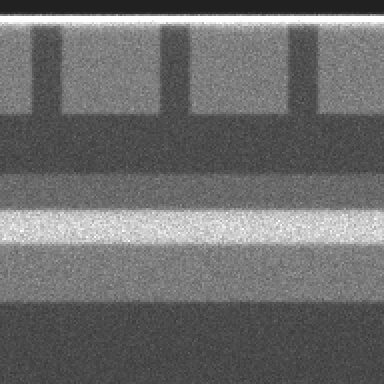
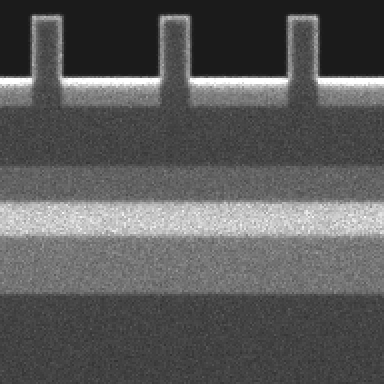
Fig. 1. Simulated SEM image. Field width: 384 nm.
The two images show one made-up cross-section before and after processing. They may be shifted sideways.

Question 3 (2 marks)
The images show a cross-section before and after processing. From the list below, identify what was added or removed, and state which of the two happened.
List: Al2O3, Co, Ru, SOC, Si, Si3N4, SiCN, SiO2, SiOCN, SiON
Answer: SOC was removed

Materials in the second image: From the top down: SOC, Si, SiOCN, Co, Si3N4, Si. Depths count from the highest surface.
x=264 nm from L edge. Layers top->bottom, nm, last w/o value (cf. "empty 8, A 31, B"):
empty 62, SOC 28, Si 60, SiOCN 36, Co 34, Si3N4 58, Si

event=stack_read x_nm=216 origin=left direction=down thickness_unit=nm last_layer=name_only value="empty 62, SOC 28, Si 60, SiOCN 36, Co 34, Si3N4 58, Si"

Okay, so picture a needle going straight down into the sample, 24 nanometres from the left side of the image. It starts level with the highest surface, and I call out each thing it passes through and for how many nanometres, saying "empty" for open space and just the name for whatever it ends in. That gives empty 62, SOC 28, Si 60, SiOCN 36, Co 34, Si3N4 58, Si